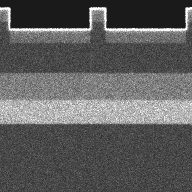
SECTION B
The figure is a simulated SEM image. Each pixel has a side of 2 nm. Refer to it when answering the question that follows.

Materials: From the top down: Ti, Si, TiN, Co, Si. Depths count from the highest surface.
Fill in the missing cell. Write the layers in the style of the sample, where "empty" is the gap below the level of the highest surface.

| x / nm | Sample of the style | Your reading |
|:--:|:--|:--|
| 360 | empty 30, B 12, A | empty 42, Ti 28, Si 60, TiN 54, Co 48, Si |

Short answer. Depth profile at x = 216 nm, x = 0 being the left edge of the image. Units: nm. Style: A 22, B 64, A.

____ empty 42, Ti 28, Si 60, TiN 54, Co 48, Si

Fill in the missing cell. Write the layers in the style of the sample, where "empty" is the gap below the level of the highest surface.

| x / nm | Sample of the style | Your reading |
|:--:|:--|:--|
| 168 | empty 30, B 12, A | empty 42, Ti 28, Si 60, TiN 54, Co 48, Si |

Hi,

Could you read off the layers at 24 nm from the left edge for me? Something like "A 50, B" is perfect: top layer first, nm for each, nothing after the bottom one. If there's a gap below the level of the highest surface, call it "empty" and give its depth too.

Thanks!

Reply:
empty 42, Ti 28, Si 60, TiN 54, Co 48, Si